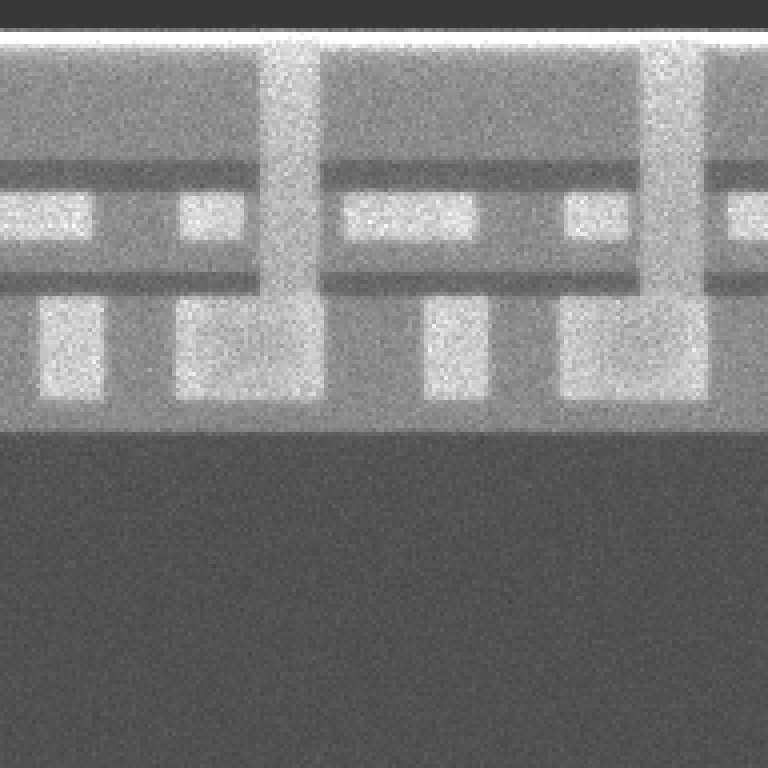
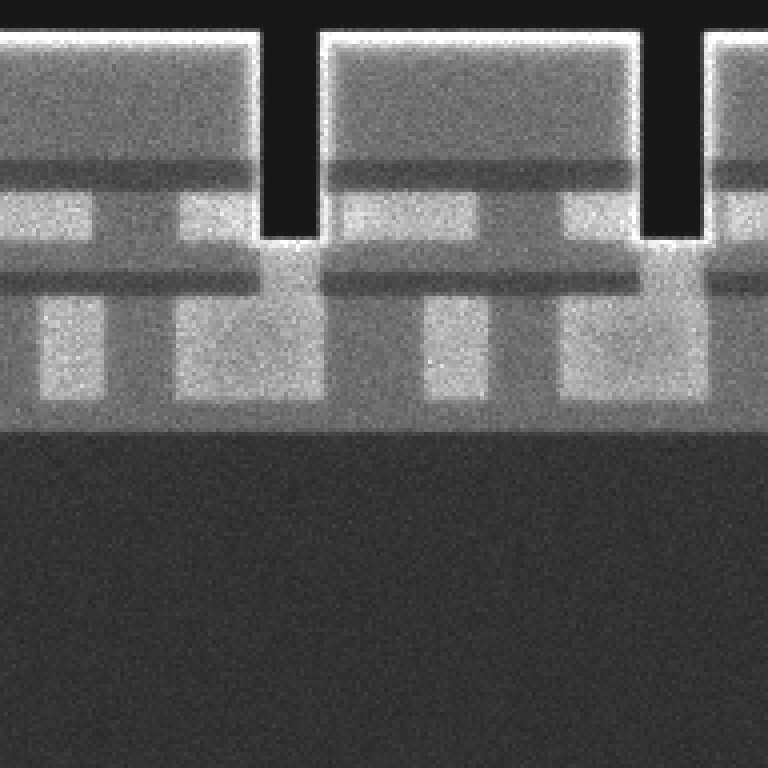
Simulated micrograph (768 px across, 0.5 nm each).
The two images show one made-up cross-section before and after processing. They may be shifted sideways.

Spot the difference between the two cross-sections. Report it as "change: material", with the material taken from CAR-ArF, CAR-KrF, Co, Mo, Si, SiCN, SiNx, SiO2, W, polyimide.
removed: Co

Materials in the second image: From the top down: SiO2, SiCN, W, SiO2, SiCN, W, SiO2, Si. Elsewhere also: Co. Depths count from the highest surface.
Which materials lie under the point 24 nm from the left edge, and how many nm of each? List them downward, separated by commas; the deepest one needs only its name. SiO2 64, SiCN 16, W 24, SiO2 16, SiCN 12, W 52, SiO2 16, Si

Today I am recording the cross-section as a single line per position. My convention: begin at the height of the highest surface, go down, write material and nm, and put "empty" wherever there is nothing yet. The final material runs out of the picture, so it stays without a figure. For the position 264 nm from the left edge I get SiO2 64, SiCN 16, SiO2 40, SiCN 12, SiO2 68, Si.